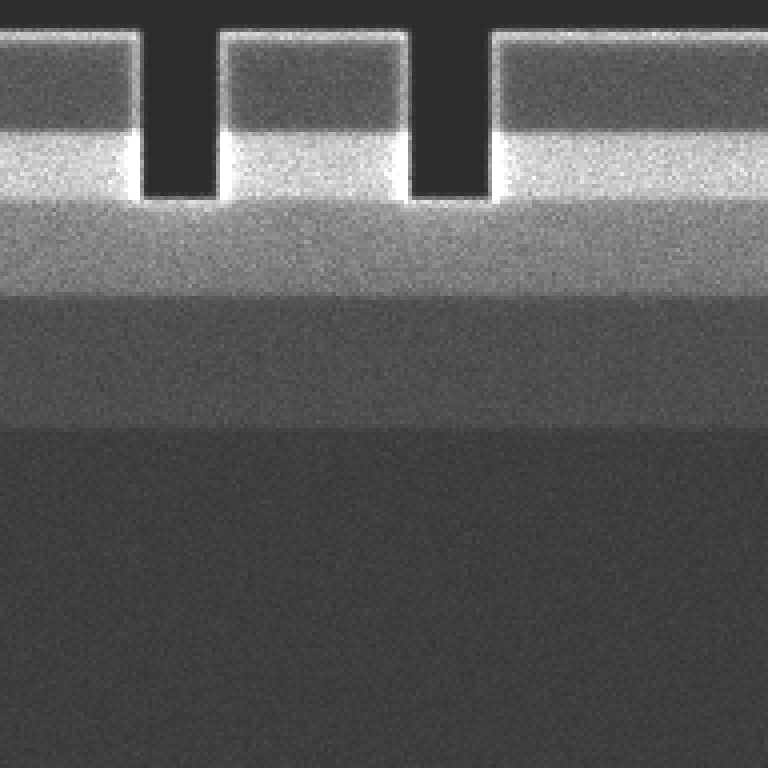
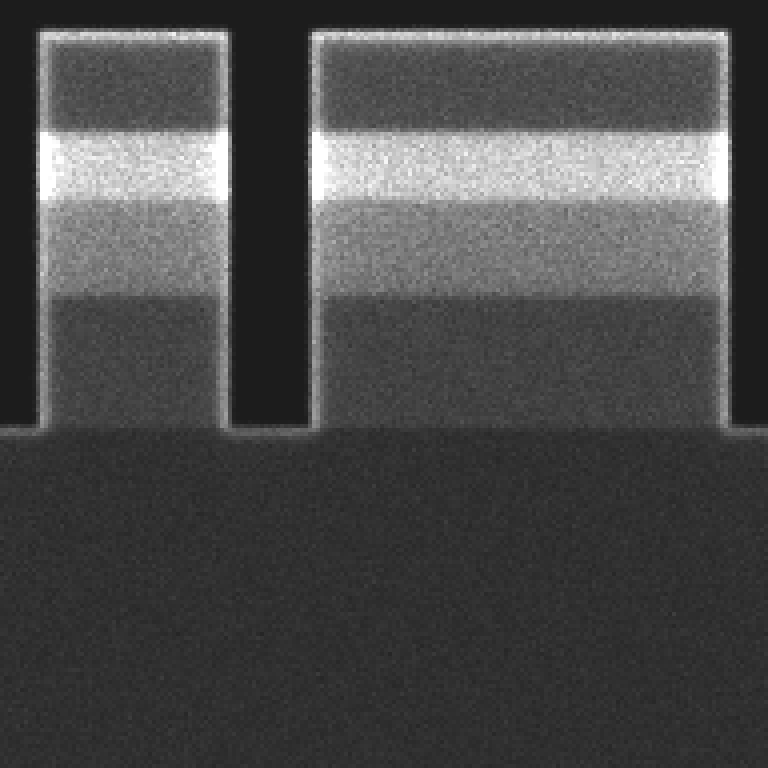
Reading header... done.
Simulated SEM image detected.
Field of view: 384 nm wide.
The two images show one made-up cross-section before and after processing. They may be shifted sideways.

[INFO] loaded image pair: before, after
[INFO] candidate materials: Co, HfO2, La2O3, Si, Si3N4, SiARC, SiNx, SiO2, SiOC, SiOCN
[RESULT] removed Co and SiNx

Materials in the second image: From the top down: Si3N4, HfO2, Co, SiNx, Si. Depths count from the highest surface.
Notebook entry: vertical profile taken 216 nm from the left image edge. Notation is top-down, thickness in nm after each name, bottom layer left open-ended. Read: Si3N4 50, HfO2 34, Co 48, SiNx 66, Si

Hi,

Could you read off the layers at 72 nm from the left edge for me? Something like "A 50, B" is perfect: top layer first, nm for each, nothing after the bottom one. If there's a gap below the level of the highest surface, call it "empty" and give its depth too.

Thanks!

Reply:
Si3N4 50, HfO2 34, Co 48, SiNx 66, Si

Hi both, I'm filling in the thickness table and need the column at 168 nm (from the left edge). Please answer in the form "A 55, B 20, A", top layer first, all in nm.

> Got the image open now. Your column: Si3N4 50, HfO2 34, Co 48, SiNx 66, Si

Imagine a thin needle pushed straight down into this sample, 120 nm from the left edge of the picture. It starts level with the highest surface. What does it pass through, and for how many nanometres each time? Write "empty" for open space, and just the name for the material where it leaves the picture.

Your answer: empty 198, Si